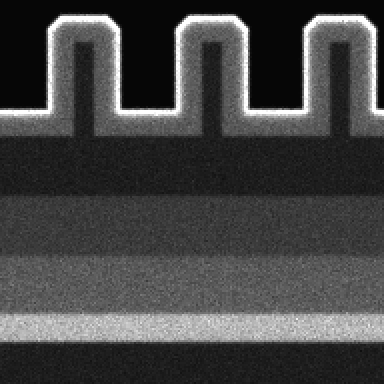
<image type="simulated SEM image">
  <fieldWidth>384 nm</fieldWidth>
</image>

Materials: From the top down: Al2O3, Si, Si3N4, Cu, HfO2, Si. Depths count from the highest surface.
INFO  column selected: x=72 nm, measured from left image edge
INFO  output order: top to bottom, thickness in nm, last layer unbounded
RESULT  Al2O3 120, Si 60, Si3N4 60, Cu 58, HfO2 28, Si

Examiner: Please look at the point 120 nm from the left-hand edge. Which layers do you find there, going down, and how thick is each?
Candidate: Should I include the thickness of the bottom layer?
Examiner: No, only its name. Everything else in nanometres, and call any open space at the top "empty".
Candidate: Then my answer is empty 94, Al2O3 26, Si 60, Si3N4 60, Cu 58, HfO2 28, Si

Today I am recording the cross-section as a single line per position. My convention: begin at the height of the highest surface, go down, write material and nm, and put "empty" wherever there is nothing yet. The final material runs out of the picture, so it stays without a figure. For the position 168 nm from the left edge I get empty 94, Al2O3 26, Si 60, Si3N4 60, Cu 58, HfO2 28, Si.